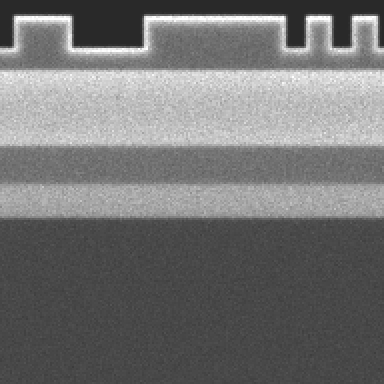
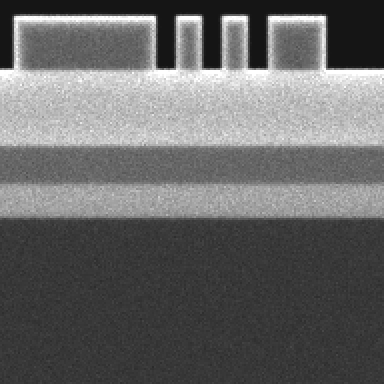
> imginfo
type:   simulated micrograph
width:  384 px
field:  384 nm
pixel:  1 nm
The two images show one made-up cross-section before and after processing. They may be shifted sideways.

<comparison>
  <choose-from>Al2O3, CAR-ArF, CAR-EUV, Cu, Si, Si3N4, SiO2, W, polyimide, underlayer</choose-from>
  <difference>underlayer removed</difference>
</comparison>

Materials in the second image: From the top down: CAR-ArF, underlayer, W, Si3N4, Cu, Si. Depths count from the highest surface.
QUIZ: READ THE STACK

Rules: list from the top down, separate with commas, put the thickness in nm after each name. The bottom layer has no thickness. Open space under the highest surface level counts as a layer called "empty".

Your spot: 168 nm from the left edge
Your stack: empty 54, W 76, Si3N4 38, Cu 34, Si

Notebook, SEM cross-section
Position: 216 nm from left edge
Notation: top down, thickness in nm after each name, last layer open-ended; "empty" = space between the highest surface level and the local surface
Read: empty 54, W 76, Si3N4 38, Cu 34, Si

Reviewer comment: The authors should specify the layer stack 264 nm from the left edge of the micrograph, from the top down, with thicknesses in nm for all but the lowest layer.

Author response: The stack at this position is empty 54, W 76, Si3N4 38, Cu 34, Si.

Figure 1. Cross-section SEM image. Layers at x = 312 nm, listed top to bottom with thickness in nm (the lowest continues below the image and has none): CAR-ArF 32, underlayer 22, W 76, Si3N4 38, Cu 34, Si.